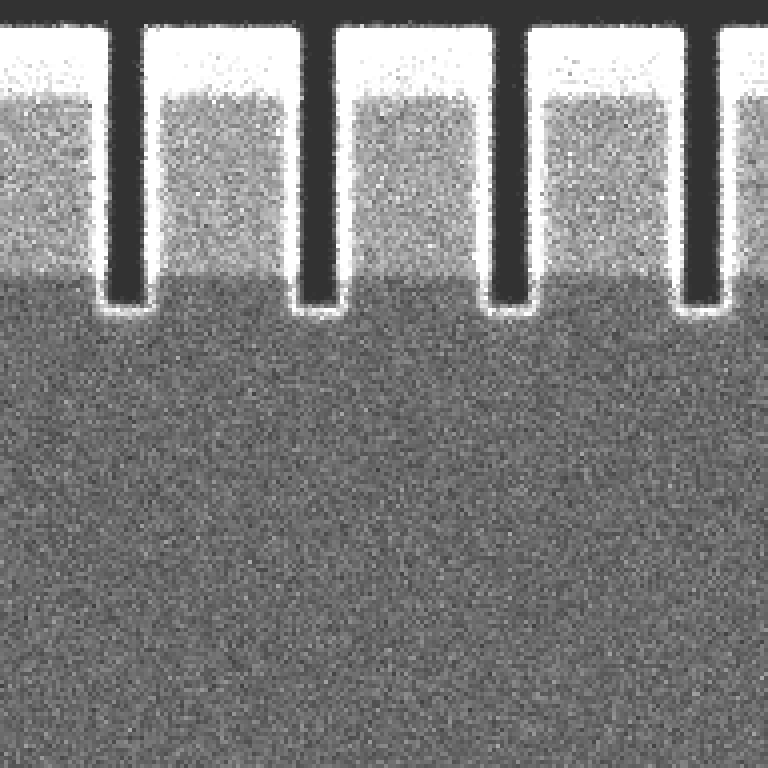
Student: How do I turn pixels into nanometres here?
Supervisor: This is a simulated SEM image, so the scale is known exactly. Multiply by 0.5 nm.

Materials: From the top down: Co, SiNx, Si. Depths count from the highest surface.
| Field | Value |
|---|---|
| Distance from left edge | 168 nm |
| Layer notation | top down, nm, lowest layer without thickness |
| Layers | empty 138, Si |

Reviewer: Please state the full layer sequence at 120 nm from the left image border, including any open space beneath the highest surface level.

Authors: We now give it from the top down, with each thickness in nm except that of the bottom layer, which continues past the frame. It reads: Co 32, SiNx 90, Si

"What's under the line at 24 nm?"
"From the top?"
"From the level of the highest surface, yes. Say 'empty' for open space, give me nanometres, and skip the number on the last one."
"Co 32, SiNx 90, Si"